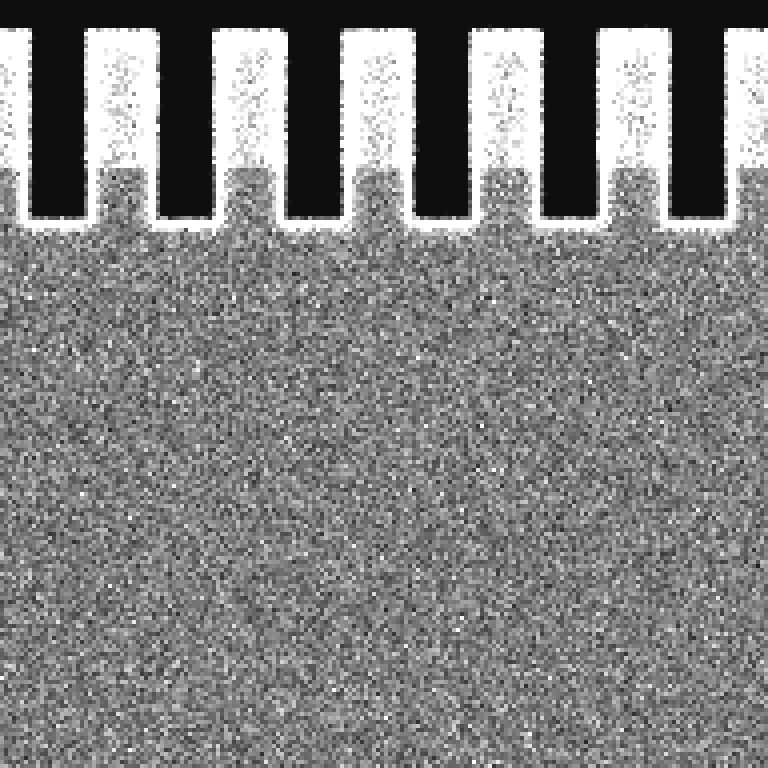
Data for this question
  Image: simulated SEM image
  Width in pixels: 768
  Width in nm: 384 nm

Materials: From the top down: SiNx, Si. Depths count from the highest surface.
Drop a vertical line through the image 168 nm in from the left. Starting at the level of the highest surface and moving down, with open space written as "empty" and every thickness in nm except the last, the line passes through empty 94, Si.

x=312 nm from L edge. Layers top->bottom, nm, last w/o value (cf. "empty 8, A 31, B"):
SiNx 68, Si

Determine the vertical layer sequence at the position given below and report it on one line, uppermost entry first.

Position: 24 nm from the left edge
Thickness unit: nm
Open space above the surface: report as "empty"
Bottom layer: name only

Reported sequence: empty 94, Si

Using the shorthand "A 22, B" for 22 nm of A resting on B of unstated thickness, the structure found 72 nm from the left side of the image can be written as SiNx 68, Si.